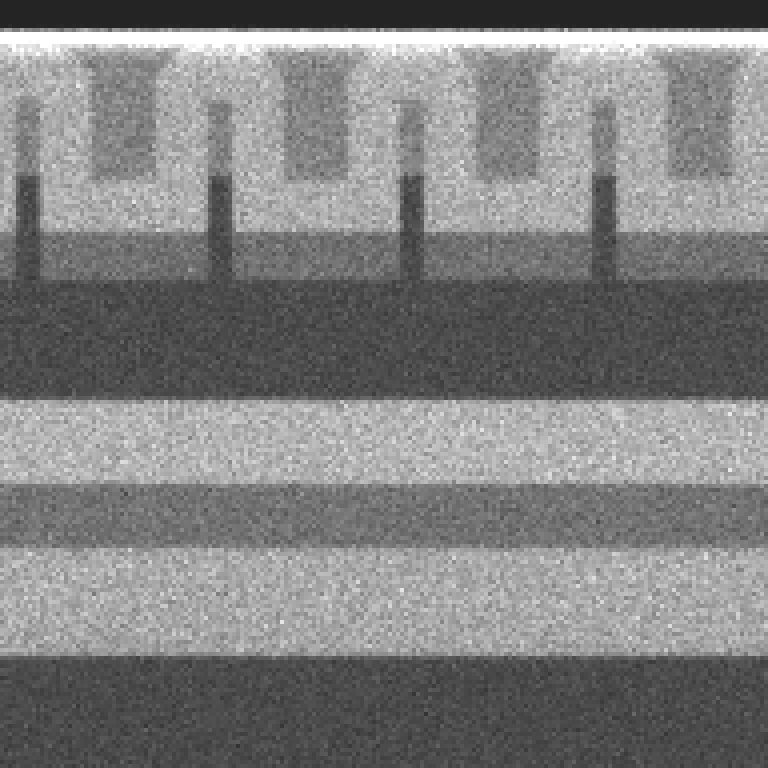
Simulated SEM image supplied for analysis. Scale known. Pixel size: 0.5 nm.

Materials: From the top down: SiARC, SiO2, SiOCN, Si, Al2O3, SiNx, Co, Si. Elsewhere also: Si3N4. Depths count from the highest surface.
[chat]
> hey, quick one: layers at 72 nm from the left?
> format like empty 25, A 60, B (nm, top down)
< SiARC 74, SiO2 26, SiOCN 24, Si 60, Al2O3 42, SiNx 32, Co 54, Si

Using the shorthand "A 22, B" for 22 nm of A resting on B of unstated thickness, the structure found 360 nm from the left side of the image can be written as SiARC 74, SiO2 26, SiOCN 24, Si 60, Al2O3 42, SiNx 32, Co 54, Si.